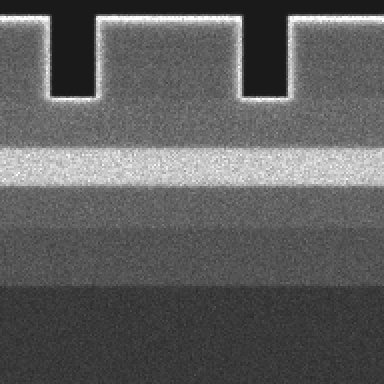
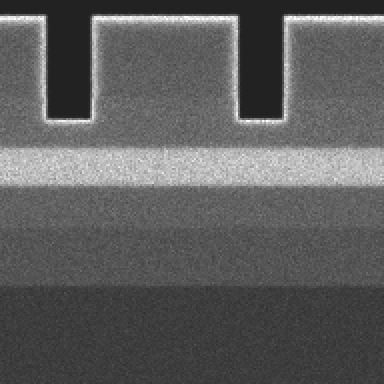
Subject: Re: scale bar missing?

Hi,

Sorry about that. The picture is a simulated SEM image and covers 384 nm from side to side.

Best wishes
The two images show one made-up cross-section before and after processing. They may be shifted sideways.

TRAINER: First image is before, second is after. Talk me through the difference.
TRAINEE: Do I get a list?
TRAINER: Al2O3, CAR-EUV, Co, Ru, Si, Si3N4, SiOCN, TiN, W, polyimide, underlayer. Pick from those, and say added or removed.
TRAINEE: removed: TiN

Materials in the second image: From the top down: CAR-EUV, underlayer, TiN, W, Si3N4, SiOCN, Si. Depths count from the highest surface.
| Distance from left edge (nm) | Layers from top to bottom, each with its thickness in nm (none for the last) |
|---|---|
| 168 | CAR-EUV 48, underlayer 34, TiN 50, W 38, Si3N4 42, SiOCN 58, Si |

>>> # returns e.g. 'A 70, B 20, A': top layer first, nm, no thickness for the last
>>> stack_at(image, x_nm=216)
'CAR-EUV 48, underlayer 34, TiN 50, W 38, Si3N4 42, SiOCN 58, Si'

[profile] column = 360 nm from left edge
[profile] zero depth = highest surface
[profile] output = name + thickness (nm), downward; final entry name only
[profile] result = CAR-EUV 48, underlayer 34, TiN 50, W 38, Si3N4 42, SiOCN 58, Si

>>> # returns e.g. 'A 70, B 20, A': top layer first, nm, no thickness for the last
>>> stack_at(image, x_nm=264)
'empty 104, TiN 28, W 38, Si3N4 42, SiOCN 58, Si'